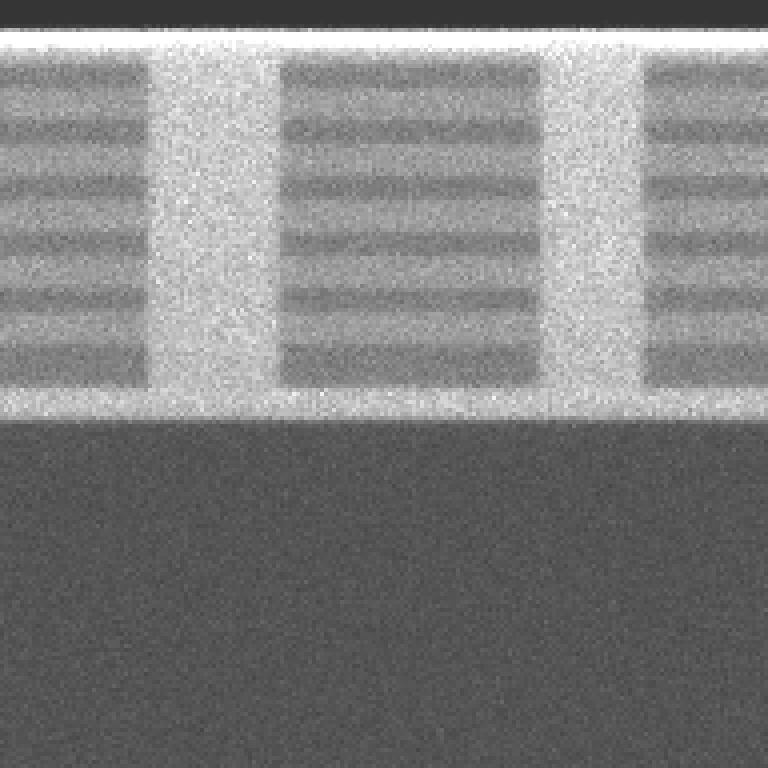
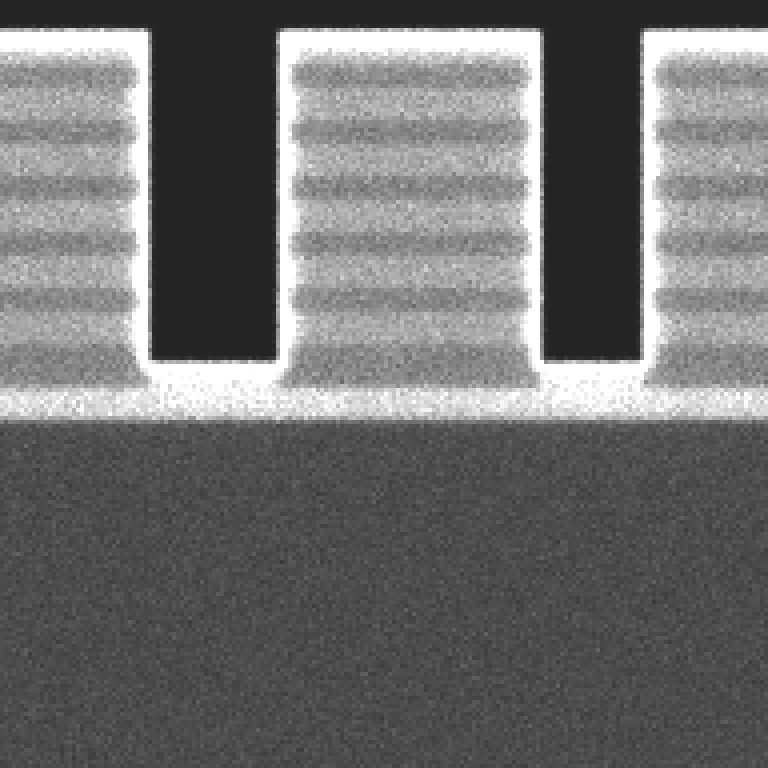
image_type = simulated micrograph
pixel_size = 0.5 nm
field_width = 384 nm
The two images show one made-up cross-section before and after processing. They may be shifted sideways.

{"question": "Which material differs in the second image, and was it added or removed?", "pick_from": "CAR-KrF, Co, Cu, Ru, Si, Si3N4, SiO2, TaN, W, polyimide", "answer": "Co, removed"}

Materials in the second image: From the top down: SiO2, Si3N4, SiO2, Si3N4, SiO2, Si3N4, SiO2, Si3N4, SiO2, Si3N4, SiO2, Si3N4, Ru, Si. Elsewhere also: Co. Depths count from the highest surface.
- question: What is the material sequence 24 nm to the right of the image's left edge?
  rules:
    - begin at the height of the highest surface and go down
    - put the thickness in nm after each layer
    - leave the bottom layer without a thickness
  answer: SiO2 16, Si3N4 12, SiO2 16, Si3N4 12, SiO2 16, Si3N4 12, SiO2 16, Si3N4 12, SiO2 16, Si3N4 12, SiO2 16, Si3N4 22, Ru 16, Si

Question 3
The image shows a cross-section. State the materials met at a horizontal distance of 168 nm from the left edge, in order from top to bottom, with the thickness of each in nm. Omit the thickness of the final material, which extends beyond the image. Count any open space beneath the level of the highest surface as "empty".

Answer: SiO2 16, Si3N4 12, SiO2 16, Si3N4 12, SiO2 16, Si3N4 12, SiO2 16, Si3N4 12, SiO2 16, Si3N4 12, SiO2 16, Si3N4 22, Ru 16, Si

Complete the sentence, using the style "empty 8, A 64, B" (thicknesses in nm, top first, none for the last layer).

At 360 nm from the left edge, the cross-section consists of SiO2 16, Si3N4 12, SiO2 16, Si3N4 12, SiO2 16, Si3N4 12, SiO2 16, Si3N4 12, SiO2 16, Si3N4 12, SiO2 16, Si3N4 22, Ru 16, Si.